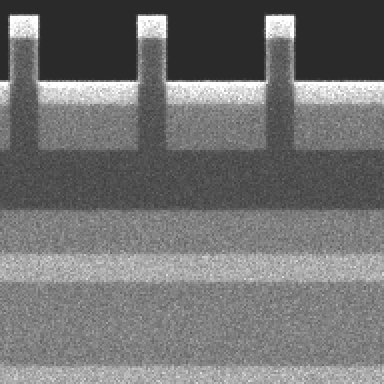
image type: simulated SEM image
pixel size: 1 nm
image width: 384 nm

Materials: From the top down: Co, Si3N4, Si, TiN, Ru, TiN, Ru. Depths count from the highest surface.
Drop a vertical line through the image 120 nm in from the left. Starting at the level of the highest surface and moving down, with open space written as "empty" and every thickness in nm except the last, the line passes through empty 66, Co 22, Si3N4 46, Si 60, TiN 44, Ru 28, TiN 84, Ru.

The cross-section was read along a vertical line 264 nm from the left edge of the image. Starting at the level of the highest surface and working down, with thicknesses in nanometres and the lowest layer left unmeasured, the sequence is empty 66, Co 22, Si3N4 46, Si 60, TiN 44, Ru 28, TiN 84, Ru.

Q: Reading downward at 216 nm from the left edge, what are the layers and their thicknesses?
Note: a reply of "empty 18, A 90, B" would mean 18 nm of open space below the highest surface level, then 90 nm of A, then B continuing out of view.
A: empty 66, Co 22, Si3N4 46, Si 60, TiN 44, Ru 28, TiN 84, Ru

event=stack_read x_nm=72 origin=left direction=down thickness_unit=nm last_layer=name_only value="empty 66, Co 22, Si3N4 46, Si 60, TiN 44, Ru 28, TiN 84, Ru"